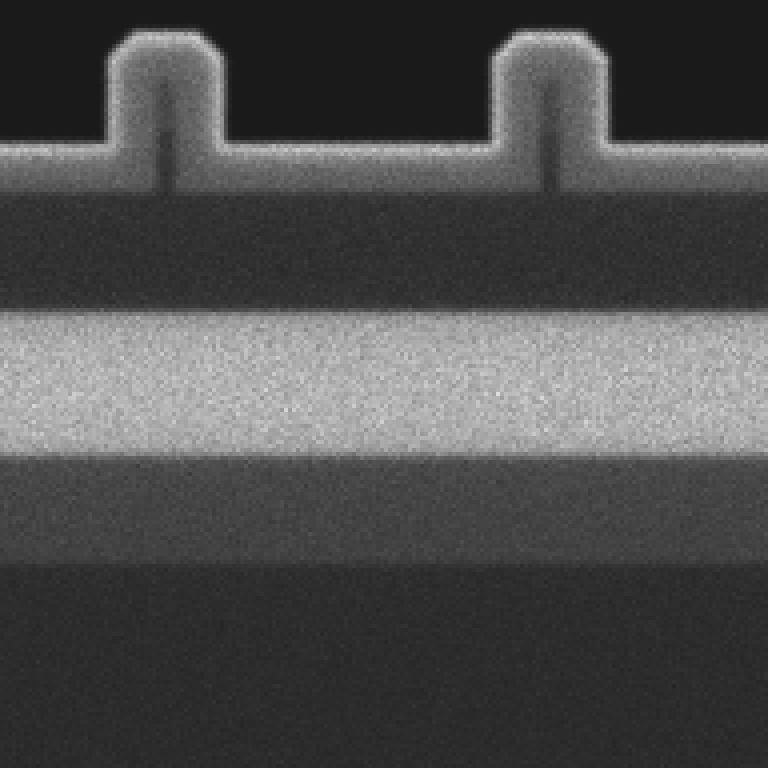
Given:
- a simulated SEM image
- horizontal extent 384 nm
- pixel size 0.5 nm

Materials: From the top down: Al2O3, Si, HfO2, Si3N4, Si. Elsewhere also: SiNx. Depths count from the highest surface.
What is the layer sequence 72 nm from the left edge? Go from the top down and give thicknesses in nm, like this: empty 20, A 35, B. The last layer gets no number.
Al2O3 80, Si 60, HfO2 72, Si3N4 54, Si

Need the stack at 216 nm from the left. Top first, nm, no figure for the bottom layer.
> empty 56, Al2O3 24, Si 60, HfO2 72, Si3N4 54, Si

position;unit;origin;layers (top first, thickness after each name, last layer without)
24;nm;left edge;empty 56, Al2O3 24, Si 60, HfO2 72, Si3N4 54, Si